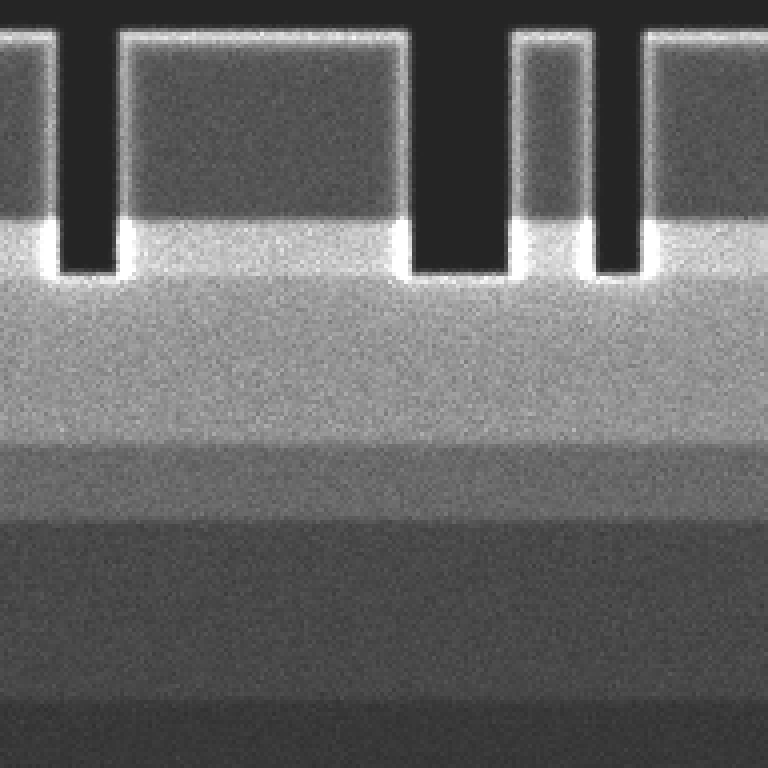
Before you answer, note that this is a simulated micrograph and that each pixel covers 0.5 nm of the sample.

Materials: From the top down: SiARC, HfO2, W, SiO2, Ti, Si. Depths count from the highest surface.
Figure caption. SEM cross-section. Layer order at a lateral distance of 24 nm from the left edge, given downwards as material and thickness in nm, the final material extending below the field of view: SiARC 94, HfO2 28, W 84, SiO2 38, Ti 90, Si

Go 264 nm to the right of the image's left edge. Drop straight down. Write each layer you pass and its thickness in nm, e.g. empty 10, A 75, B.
SiARC 94, HfO2 28, W 84, SiO2 38, Ti 90, Si